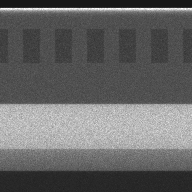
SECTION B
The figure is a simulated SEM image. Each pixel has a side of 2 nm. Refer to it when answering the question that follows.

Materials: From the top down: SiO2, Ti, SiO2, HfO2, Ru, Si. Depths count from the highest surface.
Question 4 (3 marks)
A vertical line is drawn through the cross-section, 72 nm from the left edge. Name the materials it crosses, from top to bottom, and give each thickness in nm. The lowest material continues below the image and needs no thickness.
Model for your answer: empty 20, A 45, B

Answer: SiO2 42, Ti 68, SiO2 82, HfO2 90, Ru 44, Si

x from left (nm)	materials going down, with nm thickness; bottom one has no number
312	SiO2 42, Ti 68, SiO2 82, HfO2 90, Ru 44, Si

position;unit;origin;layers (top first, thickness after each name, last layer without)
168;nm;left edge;SiO2 192, HfO2 90, Ru 44, Si